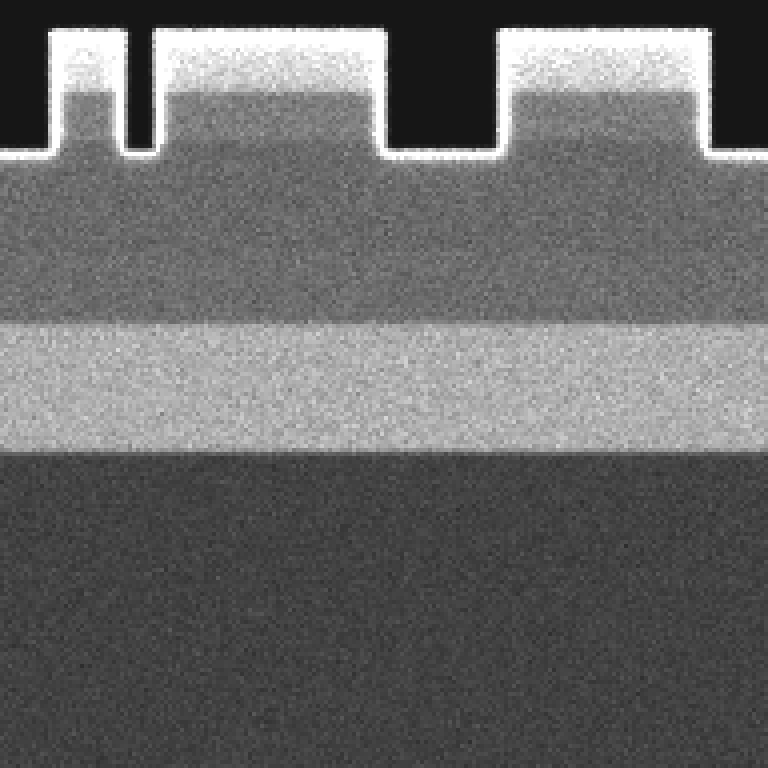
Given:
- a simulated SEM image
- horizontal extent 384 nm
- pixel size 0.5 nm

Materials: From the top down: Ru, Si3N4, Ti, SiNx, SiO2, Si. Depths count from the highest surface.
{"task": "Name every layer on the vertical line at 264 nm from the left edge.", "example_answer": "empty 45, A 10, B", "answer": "Ru 30, Si3N4 24, Ti 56, SiNx 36, SiO2 64, Si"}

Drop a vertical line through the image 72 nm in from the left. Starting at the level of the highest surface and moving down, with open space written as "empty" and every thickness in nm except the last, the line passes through empty 60, Ti 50, SiNx 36, SiO2 64, Si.